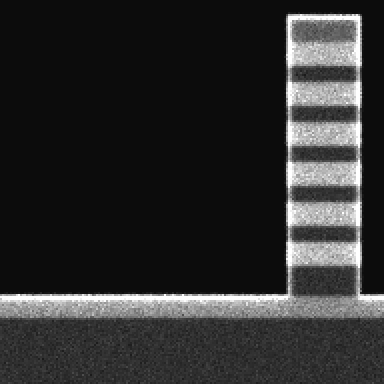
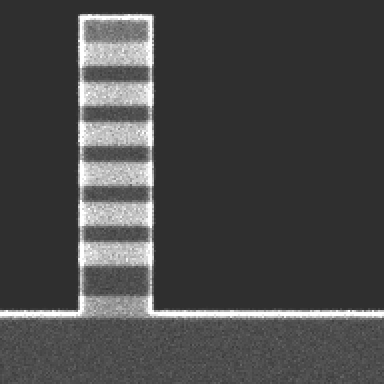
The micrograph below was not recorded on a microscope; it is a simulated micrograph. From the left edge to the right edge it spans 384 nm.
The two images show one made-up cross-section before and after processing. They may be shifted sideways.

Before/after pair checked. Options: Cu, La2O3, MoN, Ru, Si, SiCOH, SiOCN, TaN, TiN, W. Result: removed Ru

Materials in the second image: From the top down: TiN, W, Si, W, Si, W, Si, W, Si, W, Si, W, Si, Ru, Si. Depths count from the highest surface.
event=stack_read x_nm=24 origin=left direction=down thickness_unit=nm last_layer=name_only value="empty 296, Ru 6, Si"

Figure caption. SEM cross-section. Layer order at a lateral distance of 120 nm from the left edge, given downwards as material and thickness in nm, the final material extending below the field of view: TiN 26, W 24, Si 16, W 24, Si 16, W 24, Si 16, W 24, Si 16, W 24, Si 16, W 24, Si 30, Ru 22, Si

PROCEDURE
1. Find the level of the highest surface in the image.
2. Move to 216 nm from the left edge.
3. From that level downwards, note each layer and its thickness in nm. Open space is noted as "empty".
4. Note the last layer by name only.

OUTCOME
empty 296, Ru 6, Si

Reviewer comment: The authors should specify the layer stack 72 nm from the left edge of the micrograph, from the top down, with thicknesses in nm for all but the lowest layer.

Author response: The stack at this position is empty 296, Ru 6, Si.